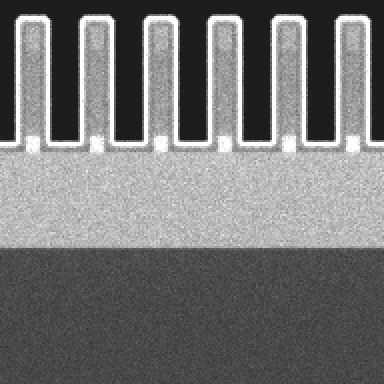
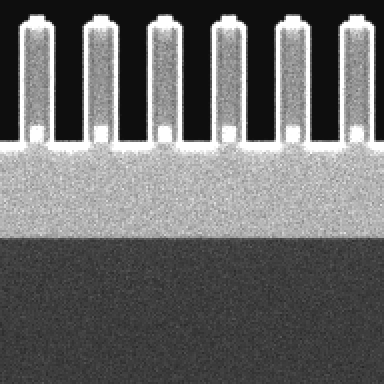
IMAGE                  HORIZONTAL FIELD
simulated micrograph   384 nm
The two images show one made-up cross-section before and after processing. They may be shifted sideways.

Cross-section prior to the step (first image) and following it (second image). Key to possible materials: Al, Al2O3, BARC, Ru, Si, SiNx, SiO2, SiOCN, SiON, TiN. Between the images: SiNx was removed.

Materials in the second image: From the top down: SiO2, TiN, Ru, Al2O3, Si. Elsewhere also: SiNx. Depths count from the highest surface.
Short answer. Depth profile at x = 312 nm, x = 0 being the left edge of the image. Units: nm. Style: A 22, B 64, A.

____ empty 126, Al2O3 96, Si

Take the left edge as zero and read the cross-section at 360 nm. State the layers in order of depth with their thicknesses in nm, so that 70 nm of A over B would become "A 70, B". SiO2 24, TiN 86, Ru 16, Al2O3 96, Si